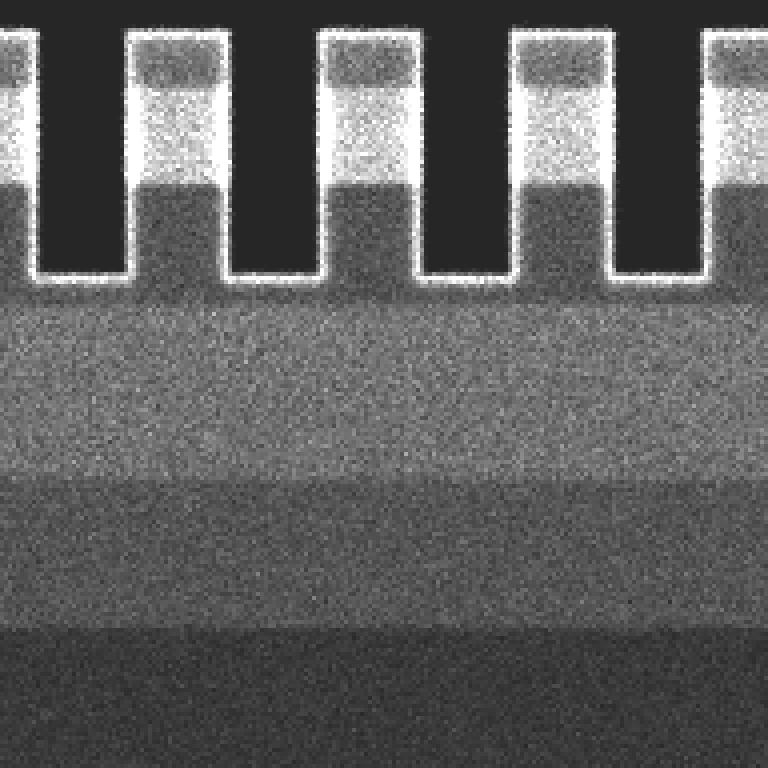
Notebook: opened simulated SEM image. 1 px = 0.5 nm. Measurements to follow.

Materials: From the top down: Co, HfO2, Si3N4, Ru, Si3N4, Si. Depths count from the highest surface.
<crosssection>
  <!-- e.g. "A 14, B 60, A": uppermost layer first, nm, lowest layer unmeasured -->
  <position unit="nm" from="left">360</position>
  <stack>Co 28, HfO2 48, Si3N4 60, Ru 88, Si3N4 74, Si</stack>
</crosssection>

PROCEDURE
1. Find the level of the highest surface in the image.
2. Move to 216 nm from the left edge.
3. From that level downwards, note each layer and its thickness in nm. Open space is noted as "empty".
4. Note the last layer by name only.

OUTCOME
empty 122, Si3N4 14, Ru 88, Si3N4 74, Si